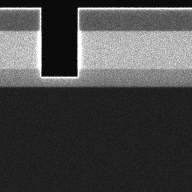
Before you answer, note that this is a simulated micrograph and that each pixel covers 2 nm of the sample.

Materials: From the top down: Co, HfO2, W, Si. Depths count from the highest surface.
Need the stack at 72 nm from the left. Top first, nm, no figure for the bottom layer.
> Co 46, HfO2 76, W 36, Si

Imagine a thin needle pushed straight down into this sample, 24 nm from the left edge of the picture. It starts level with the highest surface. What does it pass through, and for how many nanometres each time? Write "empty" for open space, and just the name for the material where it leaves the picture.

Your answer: Co 46, HfO2 76, W 36, Si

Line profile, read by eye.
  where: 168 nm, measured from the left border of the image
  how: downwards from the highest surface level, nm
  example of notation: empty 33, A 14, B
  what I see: Co 46, HfO2 76, W 36, Si